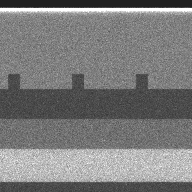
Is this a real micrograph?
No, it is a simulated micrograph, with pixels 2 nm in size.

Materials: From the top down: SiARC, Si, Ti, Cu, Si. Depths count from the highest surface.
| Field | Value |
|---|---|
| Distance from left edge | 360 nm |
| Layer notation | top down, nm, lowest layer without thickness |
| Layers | SiARC 162, Si 60, Ti 60, Cu 66, Si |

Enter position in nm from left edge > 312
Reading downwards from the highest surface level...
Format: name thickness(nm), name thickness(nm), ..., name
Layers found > SiARC 162, Si 60, Ti 60, Cu 66, Si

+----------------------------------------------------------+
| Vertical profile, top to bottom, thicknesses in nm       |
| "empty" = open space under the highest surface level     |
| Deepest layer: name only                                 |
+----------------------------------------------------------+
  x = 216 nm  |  SiARC 162, Si 60, Ti 60, Cu 66, Si